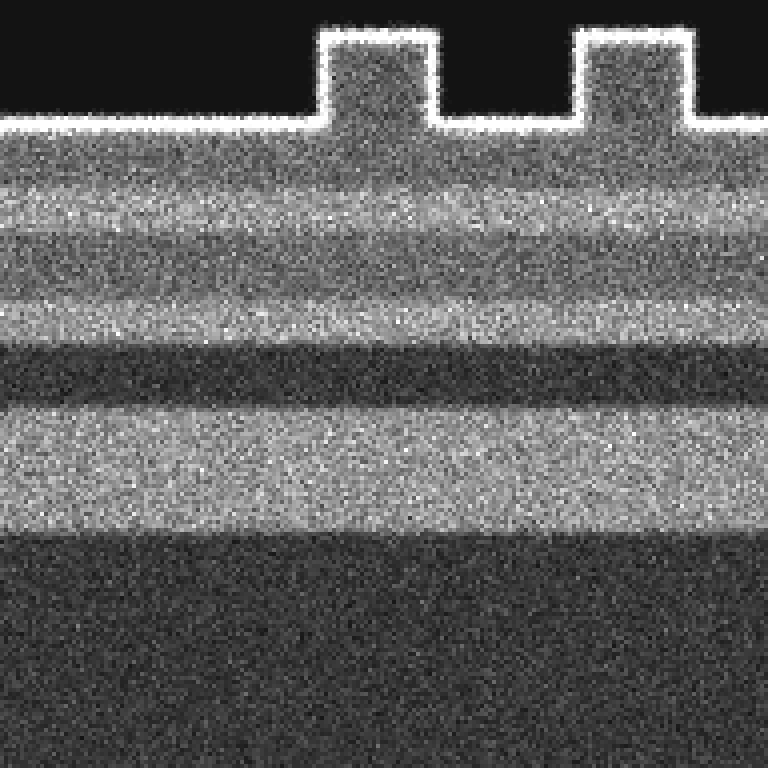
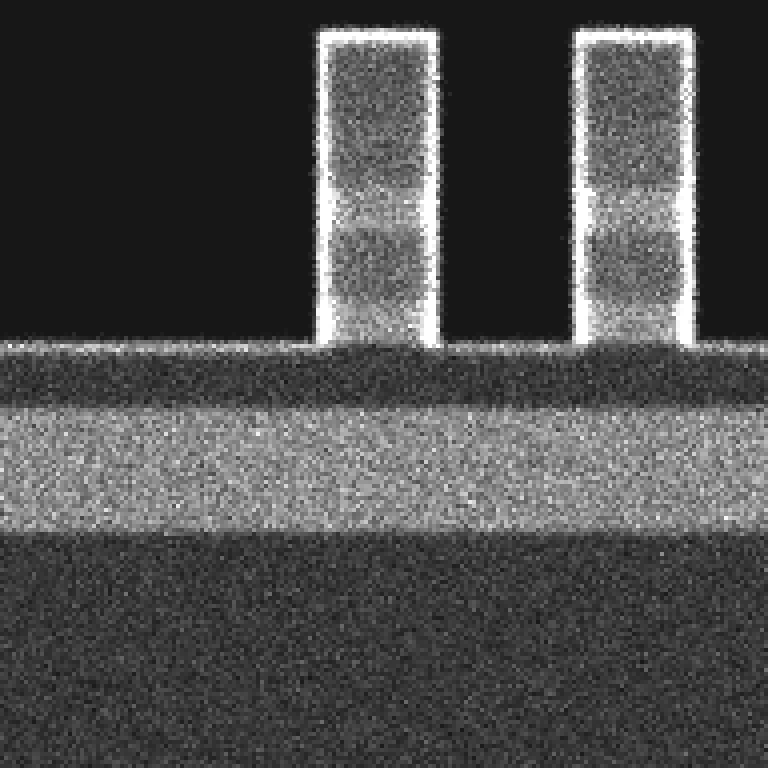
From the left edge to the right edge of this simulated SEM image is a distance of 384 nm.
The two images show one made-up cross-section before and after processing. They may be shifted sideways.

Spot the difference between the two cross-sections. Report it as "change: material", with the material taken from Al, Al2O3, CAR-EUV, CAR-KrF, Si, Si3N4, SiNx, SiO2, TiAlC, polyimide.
removed: Al2O3 and Si3N4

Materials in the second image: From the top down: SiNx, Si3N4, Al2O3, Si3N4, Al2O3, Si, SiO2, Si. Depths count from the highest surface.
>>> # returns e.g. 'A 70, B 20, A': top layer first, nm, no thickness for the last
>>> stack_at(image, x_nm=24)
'empty 156, Si 32, SiO2 62, Si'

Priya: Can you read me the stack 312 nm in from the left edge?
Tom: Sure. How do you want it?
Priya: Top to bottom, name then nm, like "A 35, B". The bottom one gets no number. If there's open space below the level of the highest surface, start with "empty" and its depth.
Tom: SiNx 44, Si3N4 34, Al2O3 22, Si3N4 34, Al2O3 22, Si 32, SiO2 62, Si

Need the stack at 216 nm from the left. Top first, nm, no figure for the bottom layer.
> SiNx 44, Si3N4 34, Al2O3 22, Si3N4 34, Al2O3 22, Si 32, SiO2 62, Si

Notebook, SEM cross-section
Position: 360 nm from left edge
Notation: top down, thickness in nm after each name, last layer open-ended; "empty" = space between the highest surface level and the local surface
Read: empty 156, Si 32, SiO2 62, Si